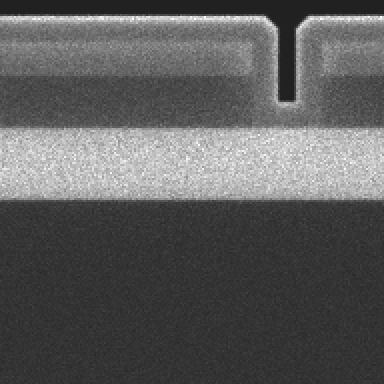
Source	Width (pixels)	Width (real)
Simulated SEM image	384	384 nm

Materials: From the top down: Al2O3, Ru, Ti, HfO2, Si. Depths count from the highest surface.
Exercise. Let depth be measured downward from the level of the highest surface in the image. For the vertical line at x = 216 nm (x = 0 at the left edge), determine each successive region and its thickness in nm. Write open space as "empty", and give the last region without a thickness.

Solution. Al2O3 26, Ru 34, Ti 52, HfO2 72, Si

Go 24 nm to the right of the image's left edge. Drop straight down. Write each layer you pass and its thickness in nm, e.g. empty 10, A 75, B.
Al2O3 26, Ru 34, Ti 52, HfO2 72, Si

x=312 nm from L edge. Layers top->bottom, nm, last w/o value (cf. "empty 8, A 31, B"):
Al2O3 112, HfO2 72, Si